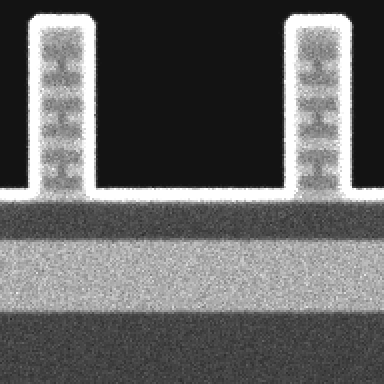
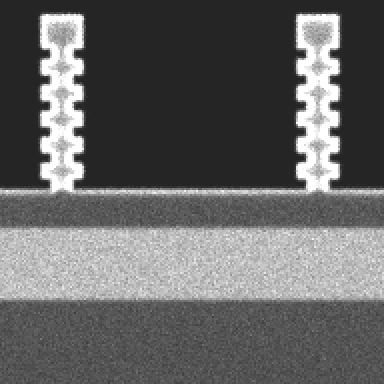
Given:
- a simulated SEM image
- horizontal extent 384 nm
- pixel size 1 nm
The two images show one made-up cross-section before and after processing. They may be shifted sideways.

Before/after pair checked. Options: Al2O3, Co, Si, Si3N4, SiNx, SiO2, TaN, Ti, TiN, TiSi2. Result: removed Al2O3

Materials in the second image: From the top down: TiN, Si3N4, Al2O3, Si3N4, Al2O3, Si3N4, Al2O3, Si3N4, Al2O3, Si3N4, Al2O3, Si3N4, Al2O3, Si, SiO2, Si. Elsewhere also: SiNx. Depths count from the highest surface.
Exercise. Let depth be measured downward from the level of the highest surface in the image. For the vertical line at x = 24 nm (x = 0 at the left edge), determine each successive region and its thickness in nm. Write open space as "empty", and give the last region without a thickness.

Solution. empty 174, Si 38, SiO2 72, Si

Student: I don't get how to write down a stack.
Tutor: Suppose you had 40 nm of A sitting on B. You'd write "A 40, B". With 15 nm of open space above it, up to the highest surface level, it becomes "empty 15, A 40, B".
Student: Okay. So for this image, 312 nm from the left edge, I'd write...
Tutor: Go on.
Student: TiN 18, Si3N4 14, Al2O3 12, Si3N4 14, Al2O3 12, Si3N4 14, Al2O3 12, Si3N4 14, Al2O3 12, Si3N4 14, Al2O3 12, Si3N4 14, Al2O3 12, Si 38, SiO2 72, Si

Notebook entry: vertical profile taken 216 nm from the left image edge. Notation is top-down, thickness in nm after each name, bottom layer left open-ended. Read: empty 174, Si 38, SiO2 72, Si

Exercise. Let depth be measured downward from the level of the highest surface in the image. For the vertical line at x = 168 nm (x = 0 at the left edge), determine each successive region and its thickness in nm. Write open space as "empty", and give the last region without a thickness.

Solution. empty 174, Si 38, SiO2 72, Si